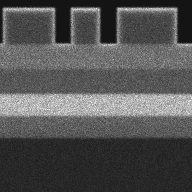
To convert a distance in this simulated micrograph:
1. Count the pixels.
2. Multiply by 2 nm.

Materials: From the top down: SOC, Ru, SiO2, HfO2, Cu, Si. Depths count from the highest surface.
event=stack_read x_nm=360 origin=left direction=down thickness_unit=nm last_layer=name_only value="empty 72, Ru 50, SiO2 50, HfO2 44, Cu 44, Si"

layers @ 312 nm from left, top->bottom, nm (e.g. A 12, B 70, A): SOC 72, Ru 50, SiO2 50, HfO2 44, Cu 44, Si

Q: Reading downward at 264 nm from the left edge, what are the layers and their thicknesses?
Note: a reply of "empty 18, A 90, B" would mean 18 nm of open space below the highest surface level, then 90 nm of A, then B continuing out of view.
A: SOC 72, Ru 50, SiO2 50, HfO2 44, Cu 44, Si